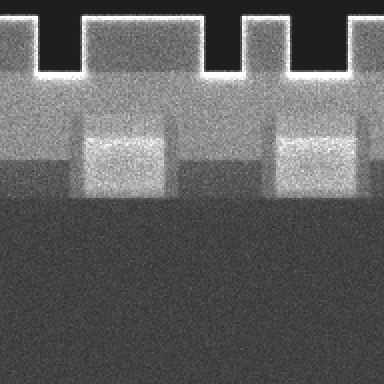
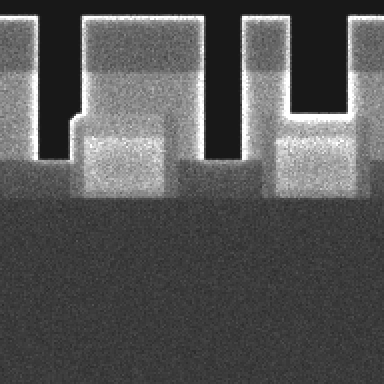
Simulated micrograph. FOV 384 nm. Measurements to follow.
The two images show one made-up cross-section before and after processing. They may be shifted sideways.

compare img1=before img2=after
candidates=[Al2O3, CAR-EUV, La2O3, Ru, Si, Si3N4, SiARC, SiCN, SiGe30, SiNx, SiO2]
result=removed:SiO2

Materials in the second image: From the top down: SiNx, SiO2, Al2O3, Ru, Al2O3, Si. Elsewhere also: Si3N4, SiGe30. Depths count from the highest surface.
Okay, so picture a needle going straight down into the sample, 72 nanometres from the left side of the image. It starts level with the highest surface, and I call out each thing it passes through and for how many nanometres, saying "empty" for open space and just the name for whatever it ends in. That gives empty 102, Si3N4 80, Si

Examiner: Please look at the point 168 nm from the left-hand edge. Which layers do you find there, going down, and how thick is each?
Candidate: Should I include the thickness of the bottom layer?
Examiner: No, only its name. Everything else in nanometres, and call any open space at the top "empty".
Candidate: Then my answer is SiNx 56, SiO2 42, Si3N4 84, Si